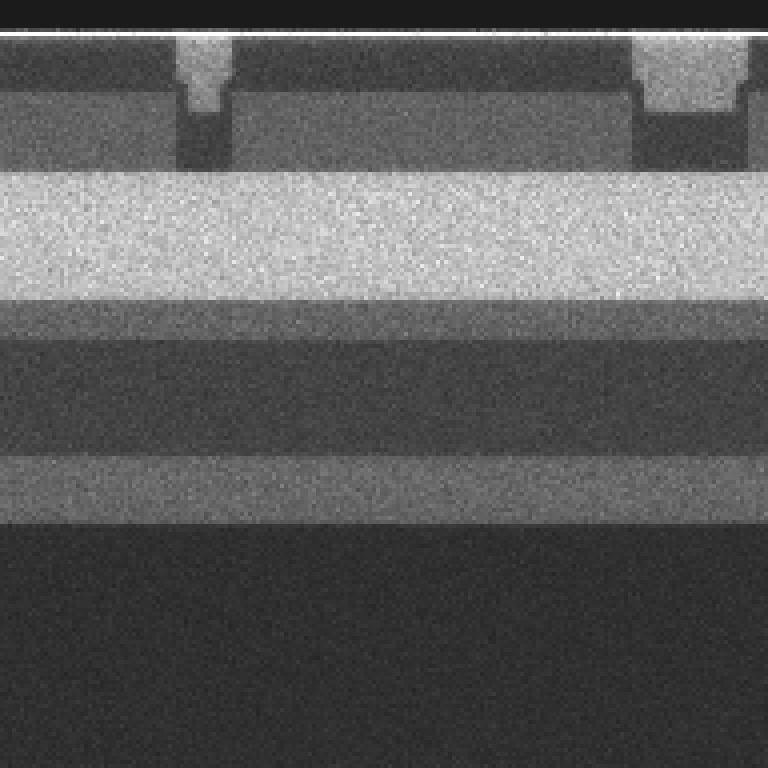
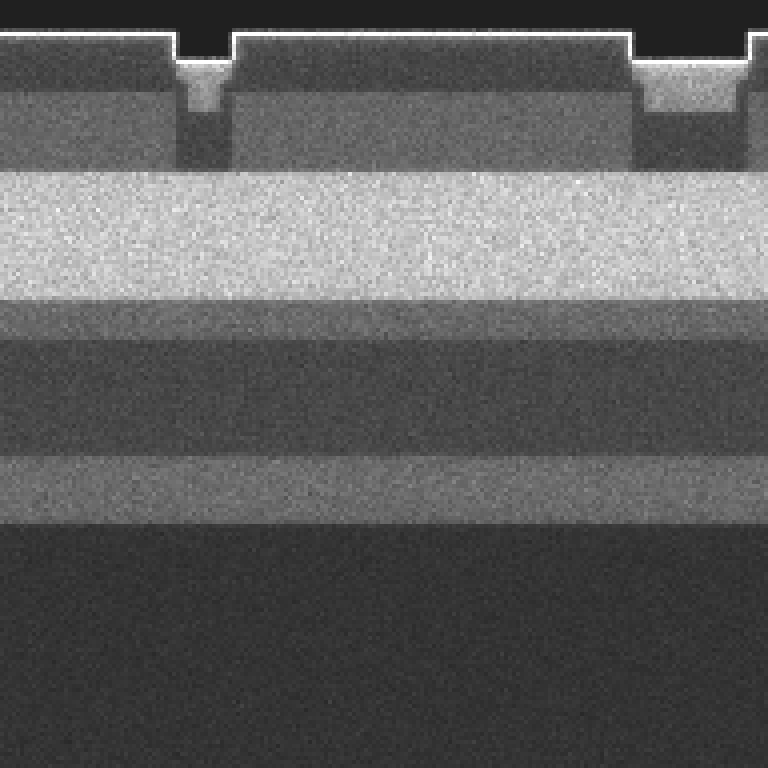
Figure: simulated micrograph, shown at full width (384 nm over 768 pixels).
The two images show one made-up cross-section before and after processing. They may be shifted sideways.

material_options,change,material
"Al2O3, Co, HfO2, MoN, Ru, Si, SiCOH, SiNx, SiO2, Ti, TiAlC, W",removed,W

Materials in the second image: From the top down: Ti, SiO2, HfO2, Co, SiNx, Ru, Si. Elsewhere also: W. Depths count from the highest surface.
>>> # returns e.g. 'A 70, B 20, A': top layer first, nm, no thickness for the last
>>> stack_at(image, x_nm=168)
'Ti 30, SiO2 40, HfO2 64, Co 20, SiNx 58, Ru 34, Si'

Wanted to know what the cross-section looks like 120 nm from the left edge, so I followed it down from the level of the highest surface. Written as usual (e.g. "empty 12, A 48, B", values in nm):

Ti 30, SiO2 40, HfO2 64, Co 20, SiNx 58, Ru 34, Si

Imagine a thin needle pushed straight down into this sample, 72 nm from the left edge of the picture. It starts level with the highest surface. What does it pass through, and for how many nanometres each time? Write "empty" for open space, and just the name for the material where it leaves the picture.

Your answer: Ti 30, SiO2 40, HfO2 64, Co 20, SiNx 58, Ru 34, Si